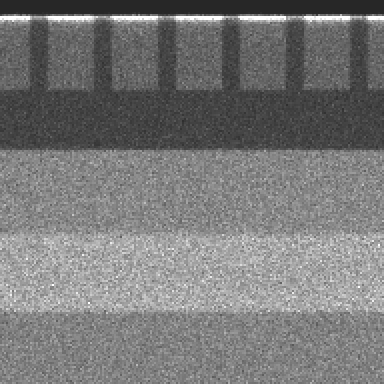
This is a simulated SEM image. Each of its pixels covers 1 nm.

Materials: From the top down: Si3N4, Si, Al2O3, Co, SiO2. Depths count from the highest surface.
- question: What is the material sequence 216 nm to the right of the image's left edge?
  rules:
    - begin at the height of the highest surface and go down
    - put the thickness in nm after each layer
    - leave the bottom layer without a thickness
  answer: Si3N4 74, Si 60, Al2O3 84, Co 78, SiO2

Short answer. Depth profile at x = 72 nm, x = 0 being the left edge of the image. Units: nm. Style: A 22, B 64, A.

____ Si3N4 74, Si 60, Al2O3 84, Co 78, SiO2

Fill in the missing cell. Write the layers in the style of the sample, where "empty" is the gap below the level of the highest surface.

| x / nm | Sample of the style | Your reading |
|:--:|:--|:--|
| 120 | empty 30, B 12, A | Si3N4 74, Si 60, Al2O3 84, Co 78, SiO2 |